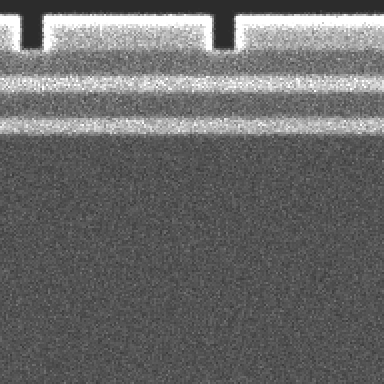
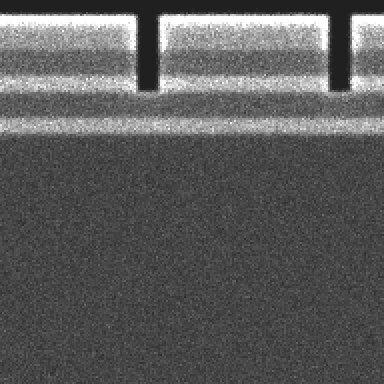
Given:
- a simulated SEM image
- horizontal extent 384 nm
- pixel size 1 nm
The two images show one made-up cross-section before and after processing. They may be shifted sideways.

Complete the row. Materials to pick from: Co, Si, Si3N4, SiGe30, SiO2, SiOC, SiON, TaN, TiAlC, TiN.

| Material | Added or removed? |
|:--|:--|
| Co and SiGe30 | removed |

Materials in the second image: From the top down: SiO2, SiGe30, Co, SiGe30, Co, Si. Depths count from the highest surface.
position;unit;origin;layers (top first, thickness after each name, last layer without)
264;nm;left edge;SiO2 34, SiGe30 26, Co 16, SiGe30 26, Co 16, Si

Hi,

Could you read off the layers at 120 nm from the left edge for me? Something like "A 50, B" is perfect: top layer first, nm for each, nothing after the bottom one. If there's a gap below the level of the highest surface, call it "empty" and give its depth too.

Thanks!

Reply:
SiO2 34, SiGe30 26, Co 16, SiGe30 26, Co 16, Si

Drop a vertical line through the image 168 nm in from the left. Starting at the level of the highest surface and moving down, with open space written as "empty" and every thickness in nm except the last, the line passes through SiO2 34, SiGe30 26, Co 16, SiGe30 26, Co 16, Si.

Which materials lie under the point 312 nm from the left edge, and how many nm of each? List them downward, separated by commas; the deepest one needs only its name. SiO2 34, SiGe30 26, Co 16, SiGe30 26, Co 16, Si